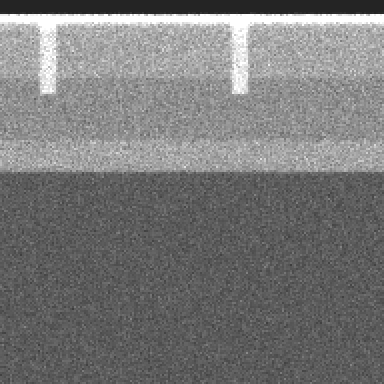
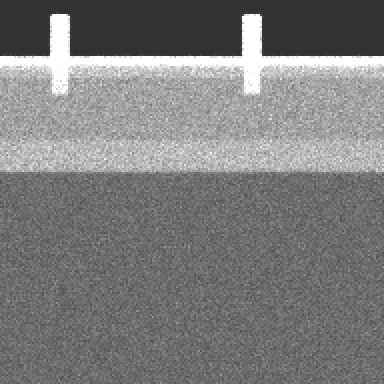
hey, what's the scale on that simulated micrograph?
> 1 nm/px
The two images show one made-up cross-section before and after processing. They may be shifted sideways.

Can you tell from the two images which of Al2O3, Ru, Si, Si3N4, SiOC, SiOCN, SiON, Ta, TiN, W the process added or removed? Yes, it removed Si3N4.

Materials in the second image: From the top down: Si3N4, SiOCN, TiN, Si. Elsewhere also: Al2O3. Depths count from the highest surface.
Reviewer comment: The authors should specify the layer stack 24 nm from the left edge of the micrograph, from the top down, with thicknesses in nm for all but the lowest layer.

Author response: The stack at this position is empty 42, Si3N4 20, SiOCN 62, TiN 32, Si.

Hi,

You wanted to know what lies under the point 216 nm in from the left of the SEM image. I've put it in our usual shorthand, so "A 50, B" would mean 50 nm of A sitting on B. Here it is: empty 42, Si3N4 20, SiOCN 62, TiN 32, Si